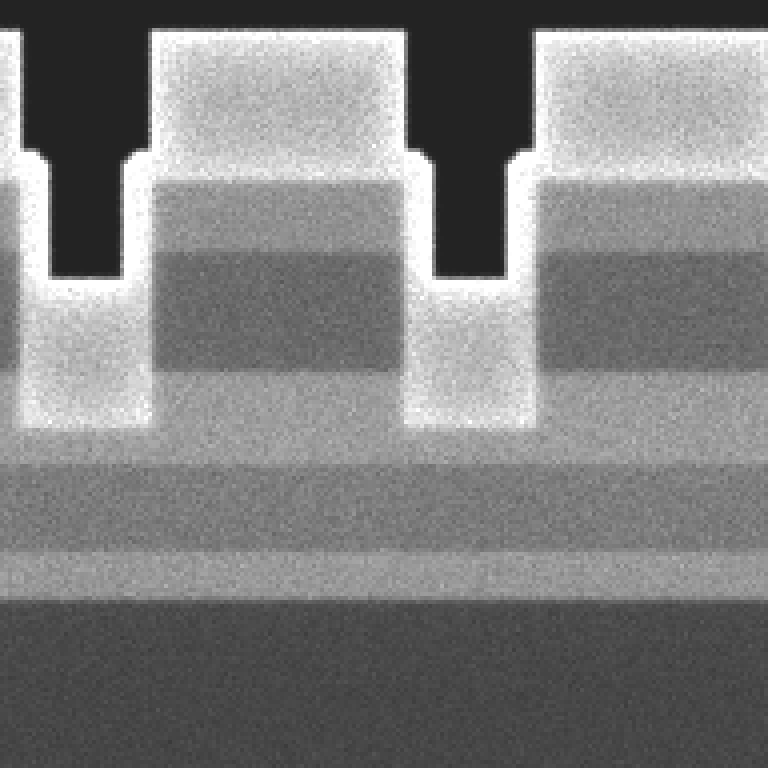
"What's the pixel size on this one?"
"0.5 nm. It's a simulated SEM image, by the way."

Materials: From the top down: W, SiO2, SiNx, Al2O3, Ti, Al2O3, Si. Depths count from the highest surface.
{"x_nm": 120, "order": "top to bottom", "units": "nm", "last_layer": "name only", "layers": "W 74, SiO2 36, SiNx 60, Al2O3 46, Ti 44, Al2O3 24, Si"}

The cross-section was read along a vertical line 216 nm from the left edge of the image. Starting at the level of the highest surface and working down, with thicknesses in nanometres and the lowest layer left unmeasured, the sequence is empty 124, W 74, Al2O3 18, Ti 44, Al2O3 24, Si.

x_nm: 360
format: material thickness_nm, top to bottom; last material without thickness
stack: W 74, SiO2 36, SiNx 60, Al2O3 46, Ti 44, Al2O3 24, Si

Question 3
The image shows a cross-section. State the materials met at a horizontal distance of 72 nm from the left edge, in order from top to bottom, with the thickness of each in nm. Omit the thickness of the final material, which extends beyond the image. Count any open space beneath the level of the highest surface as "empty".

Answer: empty 60, W 138, Al2O3 18, Ti 44, Al2O3 24, Si